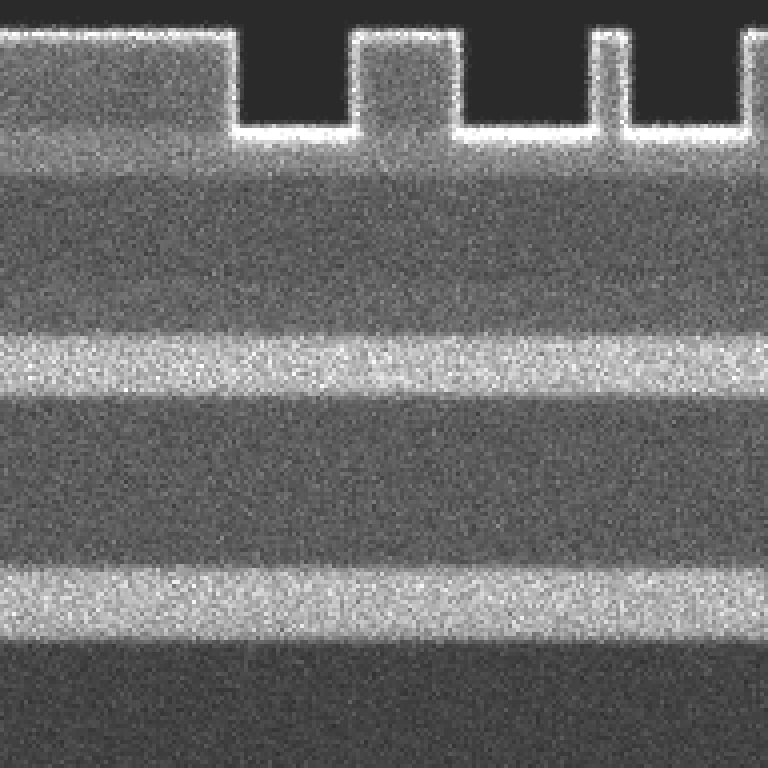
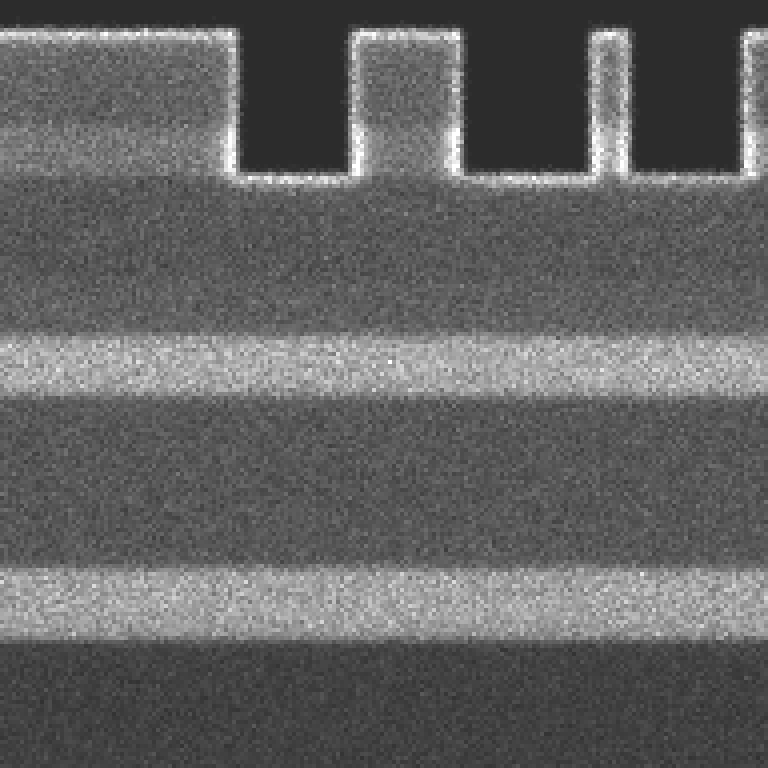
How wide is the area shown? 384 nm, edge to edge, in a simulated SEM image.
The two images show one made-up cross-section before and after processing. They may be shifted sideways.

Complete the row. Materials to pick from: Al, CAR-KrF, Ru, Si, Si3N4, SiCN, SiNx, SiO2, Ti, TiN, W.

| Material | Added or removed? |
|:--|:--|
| SiO2 | removed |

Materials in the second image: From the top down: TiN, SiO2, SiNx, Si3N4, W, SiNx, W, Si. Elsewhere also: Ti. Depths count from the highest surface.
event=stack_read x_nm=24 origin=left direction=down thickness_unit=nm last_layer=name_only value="TiN 48, SiO2 24, SiNx 52, Si3N4 28, W 30, SiNx 86, W 36, Si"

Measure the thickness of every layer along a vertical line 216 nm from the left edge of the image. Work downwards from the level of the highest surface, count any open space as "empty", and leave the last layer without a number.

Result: TiN 48, SiO2 24, Ti 52, Si3N4 28, W 30, SiNx 86, W 36, Si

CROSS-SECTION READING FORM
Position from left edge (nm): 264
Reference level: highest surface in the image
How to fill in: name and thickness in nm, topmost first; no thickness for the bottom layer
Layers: empty 72, SiNx 52, Si3N4 28, W 30, SiNx 86, W 36, Si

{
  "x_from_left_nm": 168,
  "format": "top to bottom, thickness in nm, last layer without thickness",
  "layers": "empty 72, SiNx 52, Si3N4 28, W 30, SiNx 86, W 36, Si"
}